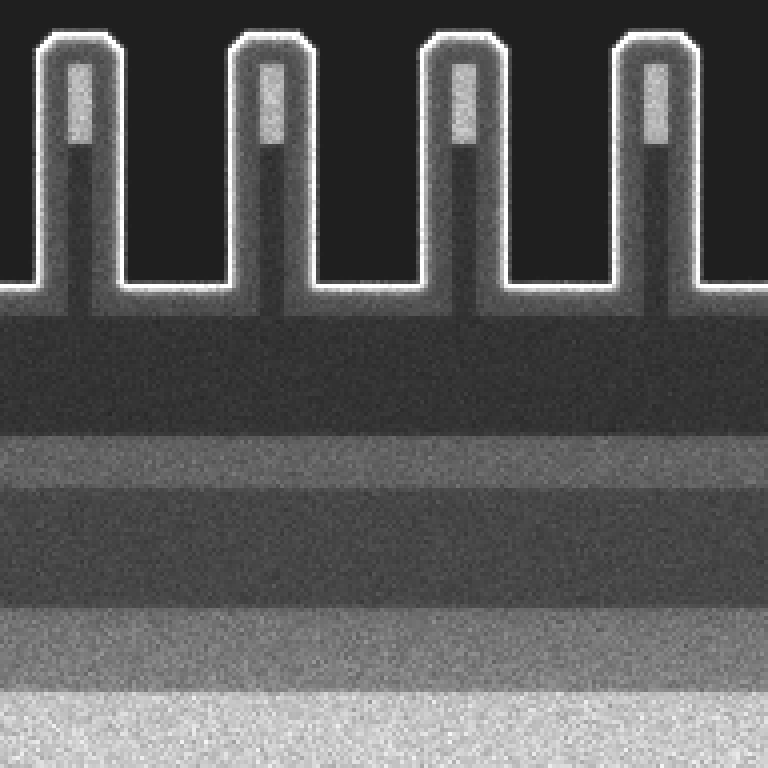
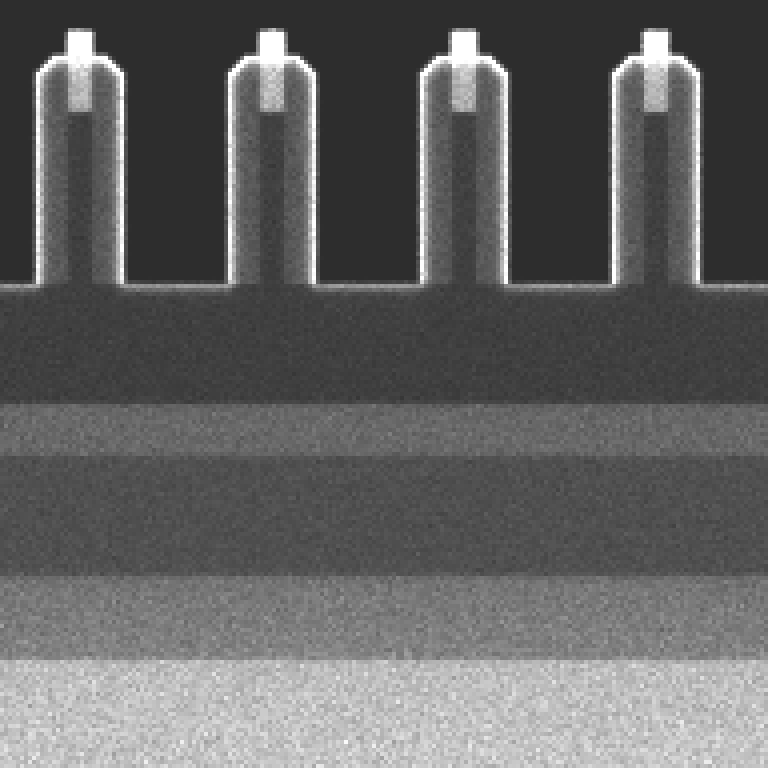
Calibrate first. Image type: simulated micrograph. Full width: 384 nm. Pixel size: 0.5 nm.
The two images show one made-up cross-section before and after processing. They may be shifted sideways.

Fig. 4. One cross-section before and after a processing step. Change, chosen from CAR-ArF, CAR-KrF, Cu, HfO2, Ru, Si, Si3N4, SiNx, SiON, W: Si3N4 removed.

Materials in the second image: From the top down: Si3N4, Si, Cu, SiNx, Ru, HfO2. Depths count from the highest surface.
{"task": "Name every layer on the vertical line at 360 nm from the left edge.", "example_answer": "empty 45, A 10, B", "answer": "empty 126, Si 60, Cu 26, SiNx 60, Ru 42, HfO2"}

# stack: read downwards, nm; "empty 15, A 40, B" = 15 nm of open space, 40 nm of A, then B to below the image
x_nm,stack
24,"empty 14, Si3N4 112, Si 60, Cu 26, SiNx 60, Ru 42, HfO2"